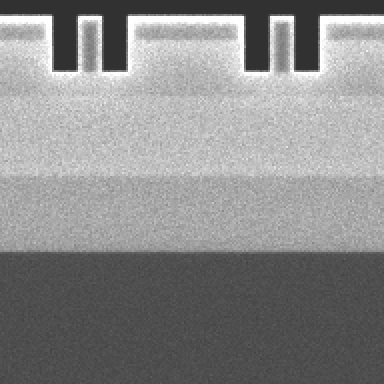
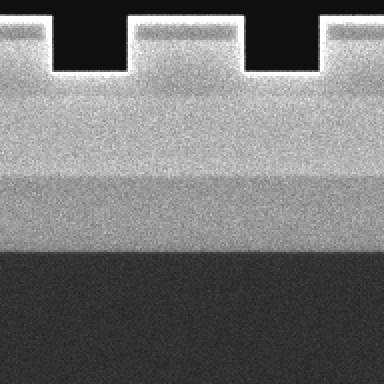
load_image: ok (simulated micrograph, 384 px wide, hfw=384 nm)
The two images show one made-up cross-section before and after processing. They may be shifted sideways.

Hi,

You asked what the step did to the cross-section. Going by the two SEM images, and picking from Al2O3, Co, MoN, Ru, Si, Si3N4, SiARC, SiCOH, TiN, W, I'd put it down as SiARC, removed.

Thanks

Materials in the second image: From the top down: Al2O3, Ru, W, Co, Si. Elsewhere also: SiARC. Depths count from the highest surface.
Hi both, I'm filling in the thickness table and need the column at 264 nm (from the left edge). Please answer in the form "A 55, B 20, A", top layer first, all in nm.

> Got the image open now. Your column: empty 56, Ru 24, W 80, Co 76, Si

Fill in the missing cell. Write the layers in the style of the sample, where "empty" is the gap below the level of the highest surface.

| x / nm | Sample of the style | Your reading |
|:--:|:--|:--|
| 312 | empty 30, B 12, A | empty 56, Ru 24, W 80, Co 76, Si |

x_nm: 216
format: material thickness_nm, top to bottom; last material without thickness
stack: Al2O3 24, Ru 56, W 80, Co 76, Si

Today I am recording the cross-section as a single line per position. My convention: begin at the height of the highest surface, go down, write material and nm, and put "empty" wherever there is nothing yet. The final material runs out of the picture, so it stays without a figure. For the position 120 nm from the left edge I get empty 56, Ru 24, W 80, Co 76, Si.